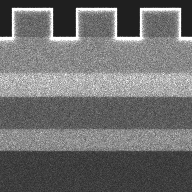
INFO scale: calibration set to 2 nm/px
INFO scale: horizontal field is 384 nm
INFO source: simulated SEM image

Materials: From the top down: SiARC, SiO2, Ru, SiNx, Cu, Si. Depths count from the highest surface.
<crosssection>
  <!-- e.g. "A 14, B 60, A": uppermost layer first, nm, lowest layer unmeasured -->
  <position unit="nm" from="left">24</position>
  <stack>SiARC 58, SiO2 72, Ru 48, SiNx 64, Cu 44, Si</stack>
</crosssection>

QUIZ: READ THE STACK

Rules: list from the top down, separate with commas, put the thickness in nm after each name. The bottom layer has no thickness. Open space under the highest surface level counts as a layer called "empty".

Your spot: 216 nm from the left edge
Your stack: SiARC 58, SiO2 72, Ru 48, SiNx 64, Cu 44, Si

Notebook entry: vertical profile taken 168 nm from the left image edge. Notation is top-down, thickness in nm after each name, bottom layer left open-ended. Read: SiARC 58, SiO2 72, Ru 48, SiNx 64, Cu 44, Si